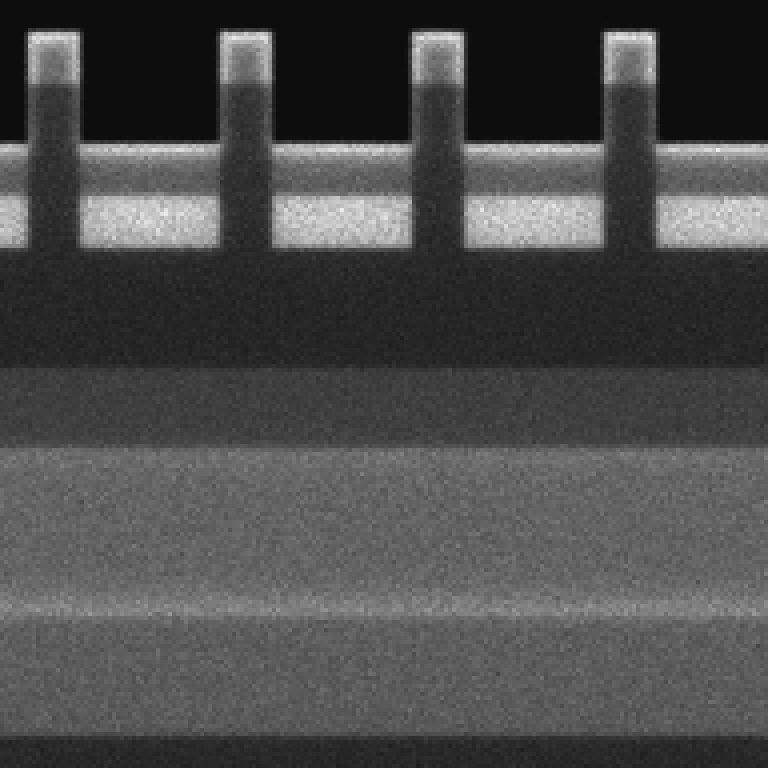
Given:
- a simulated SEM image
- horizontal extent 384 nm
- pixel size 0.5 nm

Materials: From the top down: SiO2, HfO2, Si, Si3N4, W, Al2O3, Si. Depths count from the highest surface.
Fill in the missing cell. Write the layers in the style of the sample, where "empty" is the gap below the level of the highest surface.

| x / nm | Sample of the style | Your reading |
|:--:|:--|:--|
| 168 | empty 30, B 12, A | empty 56, SiO2 26, HfO2 26, Si 60, Si3N4 40, W 84, Al2O3 60, Si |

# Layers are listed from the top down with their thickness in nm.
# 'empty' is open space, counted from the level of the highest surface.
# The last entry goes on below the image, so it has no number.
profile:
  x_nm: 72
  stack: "empty 56, SiO2 26, HfO2 26, Si 60, Si3N4 40, W 84, Al2O3 60, Si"